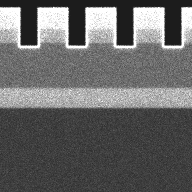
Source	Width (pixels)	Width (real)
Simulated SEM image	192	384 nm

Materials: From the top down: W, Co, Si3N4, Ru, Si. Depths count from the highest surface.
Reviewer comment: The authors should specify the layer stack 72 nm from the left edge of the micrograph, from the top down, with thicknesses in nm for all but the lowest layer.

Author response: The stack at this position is empty 76, Si3N4 84, Ru 40, Si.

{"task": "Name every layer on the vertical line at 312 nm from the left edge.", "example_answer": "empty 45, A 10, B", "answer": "W 42, Co 28, Si3N4 90, Ru 40, Si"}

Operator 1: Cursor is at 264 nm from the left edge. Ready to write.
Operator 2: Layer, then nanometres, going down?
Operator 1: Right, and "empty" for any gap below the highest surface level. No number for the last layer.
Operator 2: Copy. empty 76, Si3N4 84, Ru 40, Si